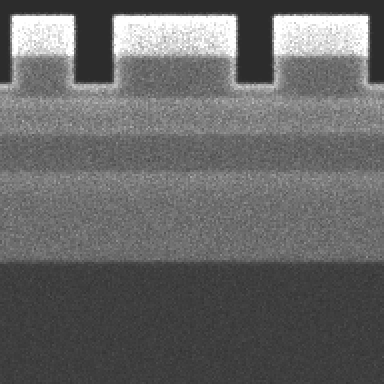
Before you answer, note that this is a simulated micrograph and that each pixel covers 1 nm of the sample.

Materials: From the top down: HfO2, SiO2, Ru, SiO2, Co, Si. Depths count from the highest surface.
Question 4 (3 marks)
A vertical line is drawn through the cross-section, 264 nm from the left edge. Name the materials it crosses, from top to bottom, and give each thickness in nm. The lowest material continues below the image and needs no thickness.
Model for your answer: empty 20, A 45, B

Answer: empty 68, SiO2 14, Ru 36, SiO2 38, Co 90, Si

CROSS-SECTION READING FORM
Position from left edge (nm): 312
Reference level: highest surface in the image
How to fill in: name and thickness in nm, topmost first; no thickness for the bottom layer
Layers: HfO2 40, SiO2 42, Ru 36, SiO2 38, Co 90, Si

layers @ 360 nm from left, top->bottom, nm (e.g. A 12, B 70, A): HfO2 40, SiO2 42, Ru 36, SiO2 38, Co 90, Si